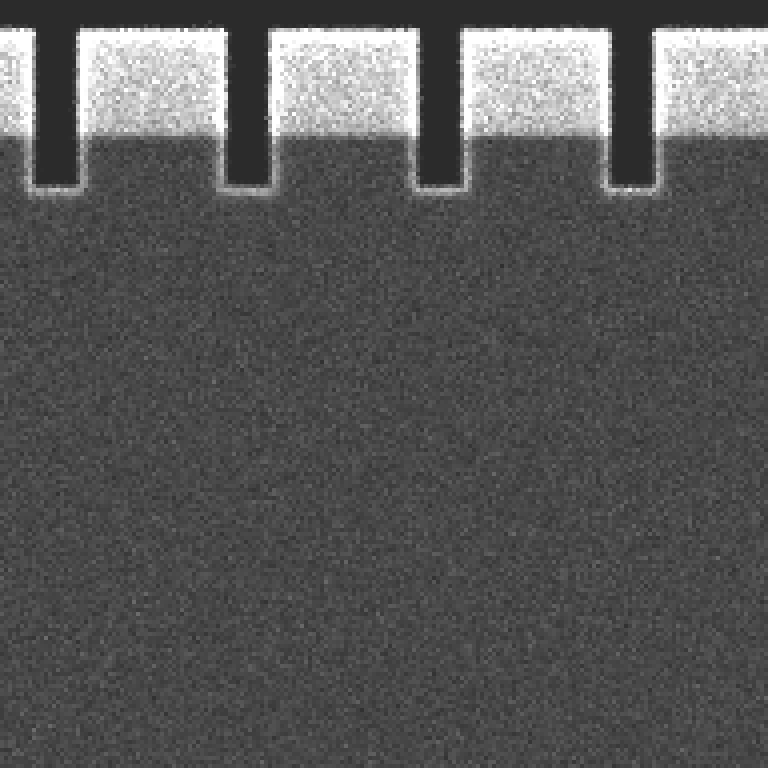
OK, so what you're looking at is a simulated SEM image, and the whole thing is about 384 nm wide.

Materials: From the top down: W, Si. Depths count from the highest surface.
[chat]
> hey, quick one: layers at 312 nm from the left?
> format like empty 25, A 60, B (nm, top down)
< empty 78, Si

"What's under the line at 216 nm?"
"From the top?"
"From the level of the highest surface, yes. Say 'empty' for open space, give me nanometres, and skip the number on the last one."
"empty 78, Si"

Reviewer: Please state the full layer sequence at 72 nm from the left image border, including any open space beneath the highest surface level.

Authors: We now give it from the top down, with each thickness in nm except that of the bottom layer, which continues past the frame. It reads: W 52, Si